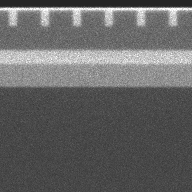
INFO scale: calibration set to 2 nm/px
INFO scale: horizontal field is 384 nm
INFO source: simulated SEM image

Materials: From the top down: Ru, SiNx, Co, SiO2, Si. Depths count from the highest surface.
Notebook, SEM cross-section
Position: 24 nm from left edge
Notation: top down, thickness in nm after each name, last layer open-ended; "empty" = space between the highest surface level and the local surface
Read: Ru 36, SiNx 48, Co 28, SiO2 46, Si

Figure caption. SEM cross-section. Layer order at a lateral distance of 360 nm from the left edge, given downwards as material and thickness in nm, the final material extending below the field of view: SiNx 84, Co 28, SiO2 46, Si